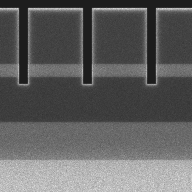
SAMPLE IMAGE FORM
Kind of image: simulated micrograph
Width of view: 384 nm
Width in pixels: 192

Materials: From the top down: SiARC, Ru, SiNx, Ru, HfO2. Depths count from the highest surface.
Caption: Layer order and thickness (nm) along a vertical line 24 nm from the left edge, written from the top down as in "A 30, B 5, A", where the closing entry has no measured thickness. SiARC 112, Ru 26, SiNx 90, Ru 76, HfO2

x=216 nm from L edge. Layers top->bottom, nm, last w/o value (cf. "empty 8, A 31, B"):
SiARC 112, Ru 26, SiNx 90, Ru 76, HfO2